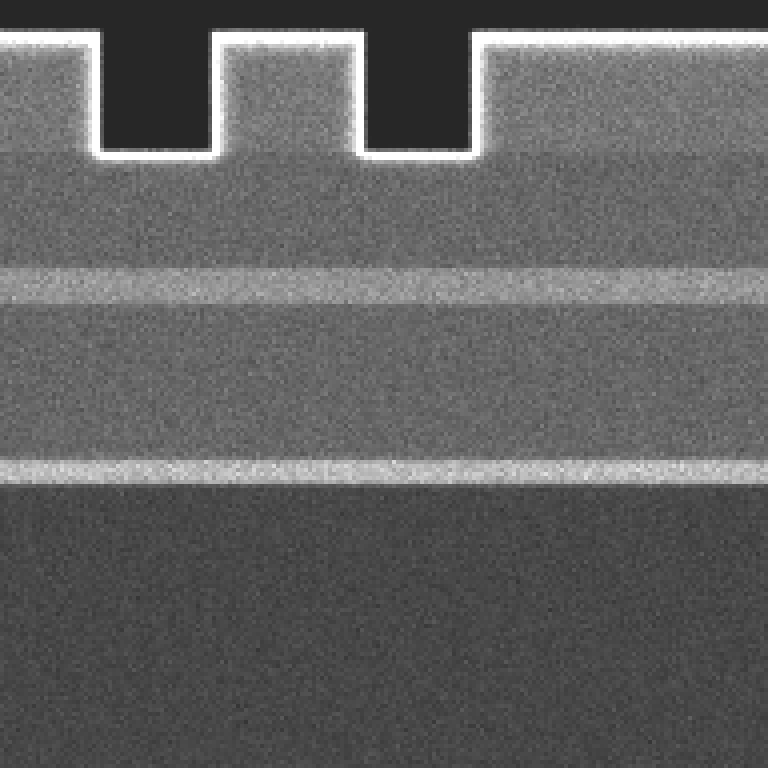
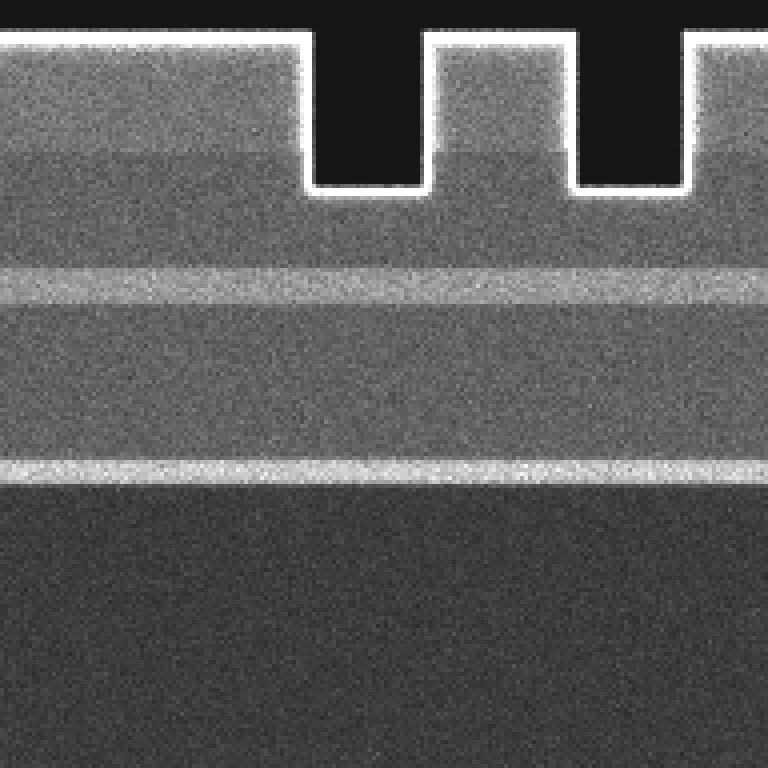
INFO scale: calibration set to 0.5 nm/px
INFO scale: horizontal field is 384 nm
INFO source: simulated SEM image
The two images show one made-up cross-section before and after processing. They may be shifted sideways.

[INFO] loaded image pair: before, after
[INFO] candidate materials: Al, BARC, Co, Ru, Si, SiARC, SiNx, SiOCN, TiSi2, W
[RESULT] removed SiNx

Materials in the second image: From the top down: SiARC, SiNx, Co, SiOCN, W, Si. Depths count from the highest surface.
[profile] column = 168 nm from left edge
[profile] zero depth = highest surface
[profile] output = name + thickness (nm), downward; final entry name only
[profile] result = empty 78, SiNx 40, Co 18, SiOCN 78, W 12, Si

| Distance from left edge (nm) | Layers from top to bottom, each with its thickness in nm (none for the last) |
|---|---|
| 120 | SiARC 60, SiNx 58, Co 18, SiOCN 78, W 12, Si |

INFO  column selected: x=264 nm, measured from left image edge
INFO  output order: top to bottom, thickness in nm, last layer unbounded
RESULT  SiARC 60, SiNx 58, Co 18, SiOCN 78, W 12, Si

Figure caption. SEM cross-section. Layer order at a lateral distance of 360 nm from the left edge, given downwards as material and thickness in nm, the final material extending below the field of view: SiARC 60, SiNx 58, Co 18, SiOCN 78, W 12, Si